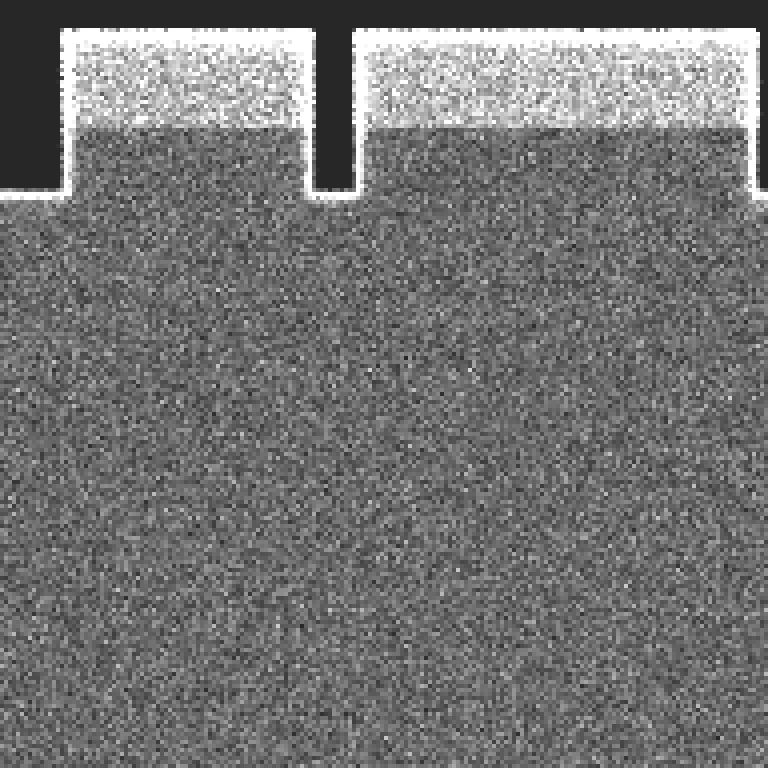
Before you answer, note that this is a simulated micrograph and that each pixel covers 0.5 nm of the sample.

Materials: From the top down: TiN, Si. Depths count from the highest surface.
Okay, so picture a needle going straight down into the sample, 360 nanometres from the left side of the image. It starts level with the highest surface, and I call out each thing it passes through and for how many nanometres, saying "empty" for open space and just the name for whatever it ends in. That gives TiN 48, Si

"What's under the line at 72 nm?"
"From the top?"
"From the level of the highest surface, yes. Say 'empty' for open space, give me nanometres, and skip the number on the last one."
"TiN 48, Si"